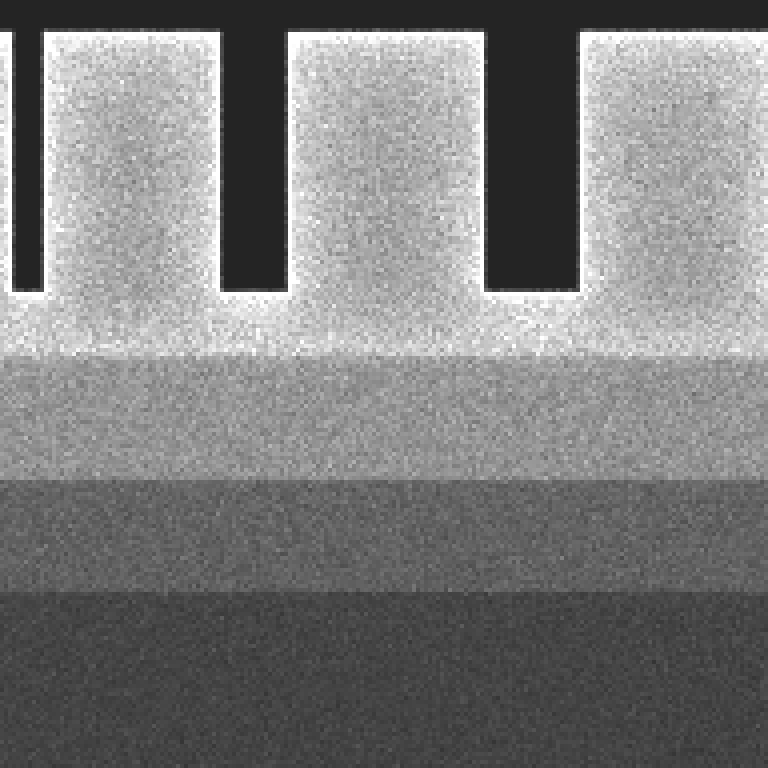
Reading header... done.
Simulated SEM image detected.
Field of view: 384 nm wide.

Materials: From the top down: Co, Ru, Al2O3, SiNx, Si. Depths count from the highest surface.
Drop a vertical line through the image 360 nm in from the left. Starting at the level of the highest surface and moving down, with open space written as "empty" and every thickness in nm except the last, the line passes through Co 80, Ru 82, Al2O3 62, SiNx 56, Si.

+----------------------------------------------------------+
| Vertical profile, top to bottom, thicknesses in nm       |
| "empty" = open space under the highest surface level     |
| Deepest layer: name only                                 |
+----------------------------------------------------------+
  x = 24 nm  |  Co 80, Ru 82, Al2O3 62, SiNx 56, Si